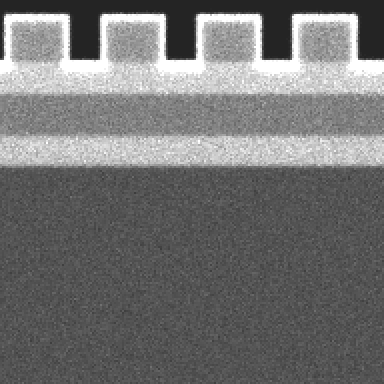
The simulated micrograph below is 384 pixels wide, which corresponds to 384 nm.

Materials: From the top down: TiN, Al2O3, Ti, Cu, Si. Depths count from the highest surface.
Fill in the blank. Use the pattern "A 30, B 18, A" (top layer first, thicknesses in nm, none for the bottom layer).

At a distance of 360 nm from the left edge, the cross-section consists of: empty 46, Al2O3 32, Ti 42, Cu 30, Si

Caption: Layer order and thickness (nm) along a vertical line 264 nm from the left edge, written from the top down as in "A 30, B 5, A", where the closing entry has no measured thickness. empty 46, Al2O3 32, Ti 42, Cu 30, Si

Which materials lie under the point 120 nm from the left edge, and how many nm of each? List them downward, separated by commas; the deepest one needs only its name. TiN 46, Al2O3 32, Ti 42, Cu 30, Si